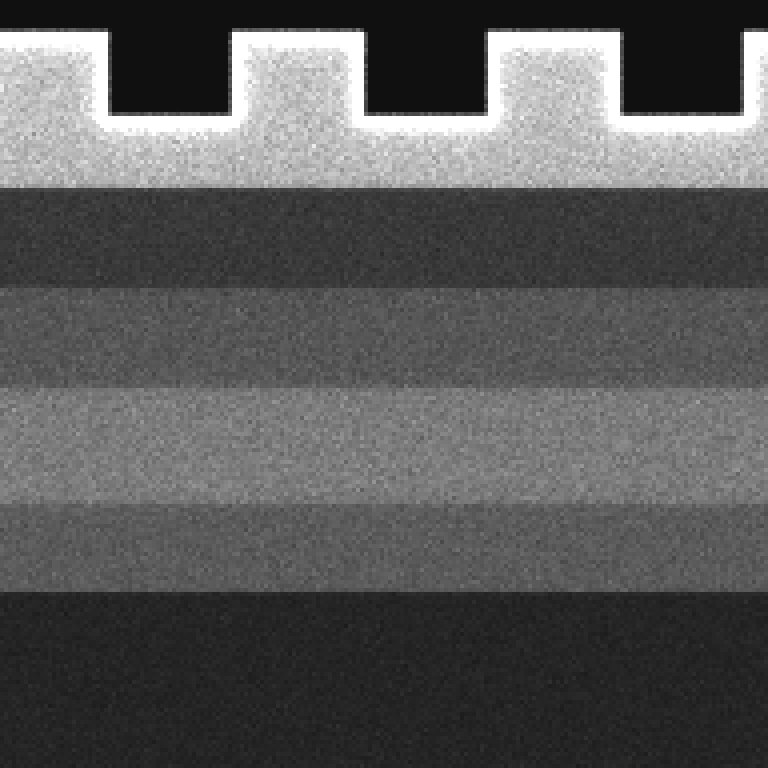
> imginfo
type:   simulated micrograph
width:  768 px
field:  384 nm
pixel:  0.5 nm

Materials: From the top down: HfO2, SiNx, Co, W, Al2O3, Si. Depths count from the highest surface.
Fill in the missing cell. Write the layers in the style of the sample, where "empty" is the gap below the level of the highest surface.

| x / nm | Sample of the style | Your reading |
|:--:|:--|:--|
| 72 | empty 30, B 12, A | empty 42, HfO2 36, SiNx 50, Co 50, W 58, Al2O3 44, Si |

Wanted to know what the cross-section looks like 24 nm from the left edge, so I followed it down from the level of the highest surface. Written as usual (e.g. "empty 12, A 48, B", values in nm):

HfO2 78, SiNx 50, Co 50, W 58, Al2O3 44, Si